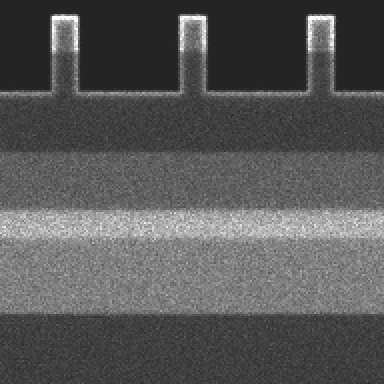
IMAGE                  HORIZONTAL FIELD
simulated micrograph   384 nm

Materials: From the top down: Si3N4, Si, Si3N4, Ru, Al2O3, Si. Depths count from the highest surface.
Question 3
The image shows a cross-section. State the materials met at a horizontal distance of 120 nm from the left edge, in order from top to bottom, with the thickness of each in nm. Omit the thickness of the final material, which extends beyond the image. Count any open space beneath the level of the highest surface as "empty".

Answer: empty 76, Si 60, Si3N4 58, Ru 28, Al2O3 76, Si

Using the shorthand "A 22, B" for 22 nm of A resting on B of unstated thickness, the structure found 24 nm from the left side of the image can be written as empty 76, Si 60, Si3N4 58, Ru 28, Al2O3 76, Si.